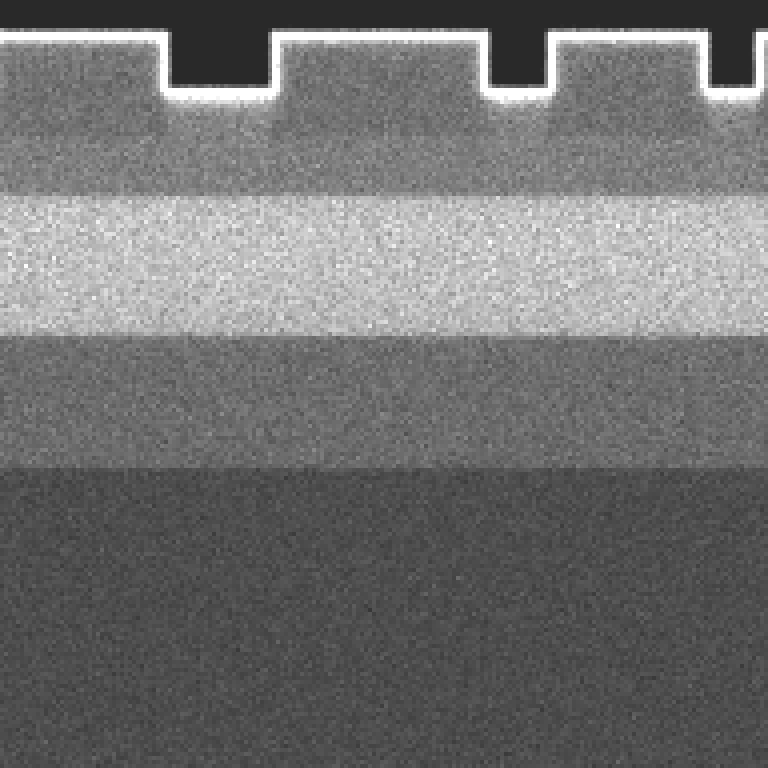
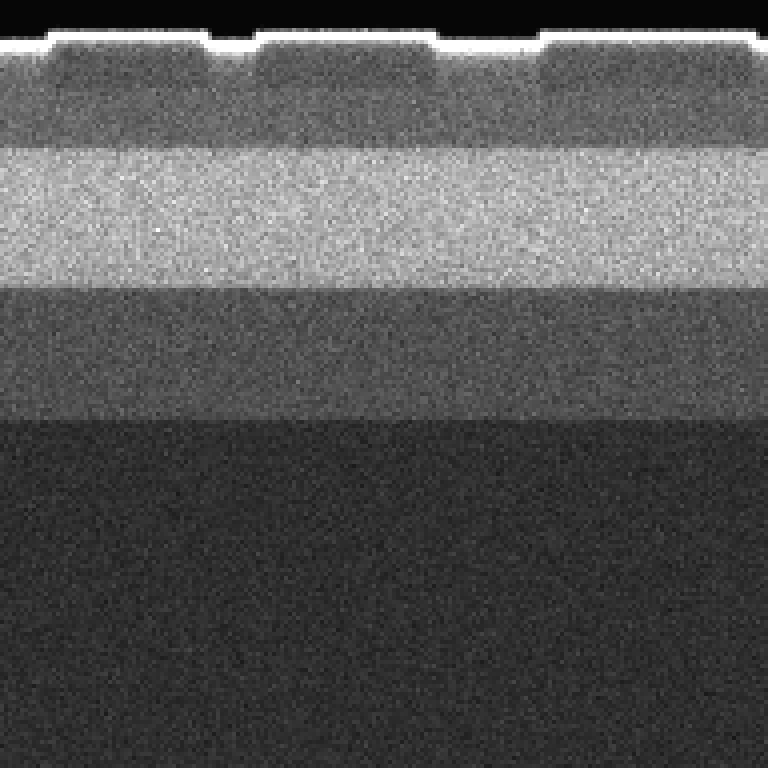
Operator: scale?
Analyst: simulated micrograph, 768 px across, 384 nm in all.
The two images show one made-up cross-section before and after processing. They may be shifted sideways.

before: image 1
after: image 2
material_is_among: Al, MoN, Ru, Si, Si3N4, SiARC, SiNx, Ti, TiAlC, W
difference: SiNx, removed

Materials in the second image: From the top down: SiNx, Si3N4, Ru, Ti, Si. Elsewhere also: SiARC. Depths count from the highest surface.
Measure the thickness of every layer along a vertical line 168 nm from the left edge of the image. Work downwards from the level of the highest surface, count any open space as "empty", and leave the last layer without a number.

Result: SiNx 28, Si3N4 30, Ru 70, Ti 66, Si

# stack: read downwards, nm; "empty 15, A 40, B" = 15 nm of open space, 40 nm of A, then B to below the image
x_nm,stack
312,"SiNx 28, Si3N4 30, Ru 70, Ti 66, Si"